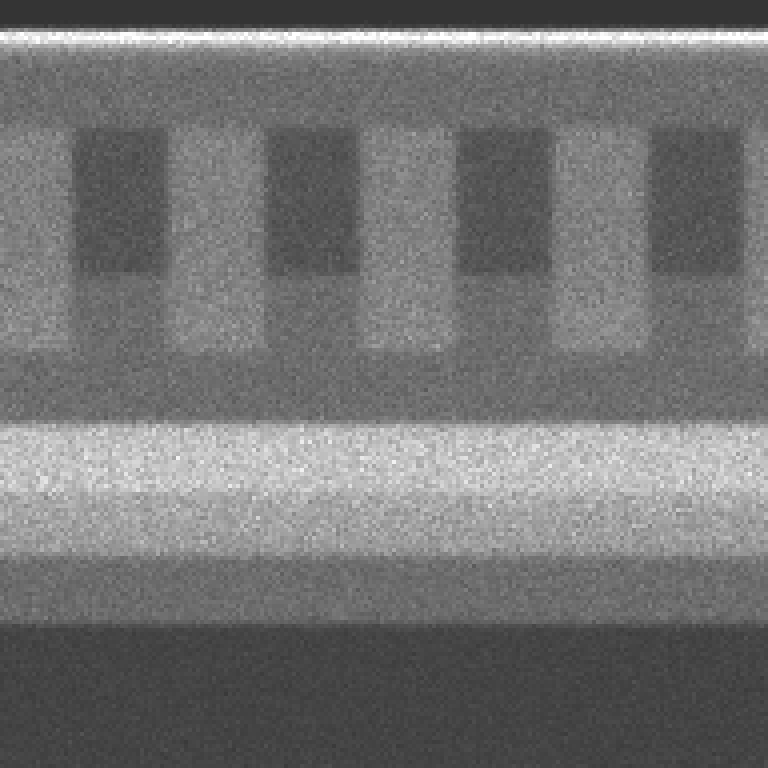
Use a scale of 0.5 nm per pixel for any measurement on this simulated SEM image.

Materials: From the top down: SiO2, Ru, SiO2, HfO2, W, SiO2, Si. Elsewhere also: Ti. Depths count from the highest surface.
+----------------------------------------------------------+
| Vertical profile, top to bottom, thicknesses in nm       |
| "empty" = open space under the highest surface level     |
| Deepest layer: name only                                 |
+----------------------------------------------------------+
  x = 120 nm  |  SiO2 48, Ru 112, SiO2 36, HfO2 34, W 32, SiO2 34, Si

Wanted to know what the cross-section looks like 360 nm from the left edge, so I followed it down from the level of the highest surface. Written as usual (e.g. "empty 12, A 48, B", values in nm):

SiO2 48, Ti 74, SiO2 74, HfO2 34, W 32, SiO2 34, Si